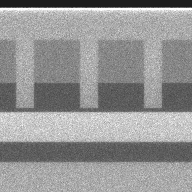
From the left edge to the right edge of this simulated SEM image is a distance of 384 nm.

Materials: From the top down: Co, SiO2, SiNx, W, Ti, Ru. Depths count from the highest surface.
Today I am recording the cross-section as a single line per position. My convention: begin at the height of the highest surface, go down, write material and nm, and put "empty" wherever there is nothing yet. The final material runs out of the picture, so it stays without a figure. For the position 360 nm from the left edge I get Co 64, SiO2 86, SiNx 58, W 60, Ti 40, Ru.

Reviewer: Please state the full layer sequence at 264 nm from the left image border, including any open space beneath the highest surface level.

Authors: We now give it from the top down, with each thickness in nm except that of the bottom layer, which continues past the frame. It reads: Co 64, SiO2 86, SiNx 58, W 60, Ti 40, Ru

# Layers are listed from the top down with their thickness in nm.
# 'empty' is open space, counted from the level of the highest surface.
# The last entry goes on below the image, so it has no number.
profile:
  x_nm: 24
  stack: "Co 64, SiO2 86, SiNx 58, W 60, Ti 40, Ru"